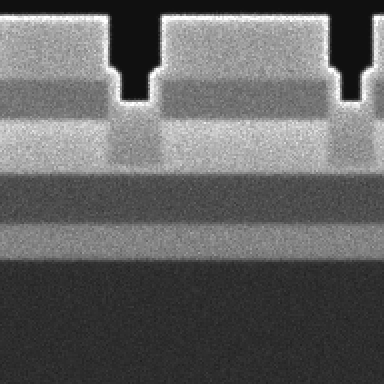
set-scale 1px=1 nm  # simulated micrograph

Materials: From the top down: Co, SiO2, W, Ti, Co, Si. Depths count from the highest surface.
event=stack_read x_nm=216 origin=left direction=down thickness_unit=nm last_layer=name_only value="Co 64, SiO2 40, W 54, Ti 50, Co 36, Si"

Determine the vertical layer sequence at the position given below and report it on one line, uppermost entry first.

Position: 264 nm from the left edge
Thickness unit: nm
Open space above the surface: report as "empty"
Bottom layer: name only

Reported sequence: Co 64, SiO2 40, W 54, Ti 50, Co 36, Si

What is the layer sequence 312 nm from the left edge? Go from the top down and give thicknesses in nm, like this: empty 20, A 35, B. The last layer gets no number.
Co 64, SiO2 40, W 54, Ti 50, Co 36, Si